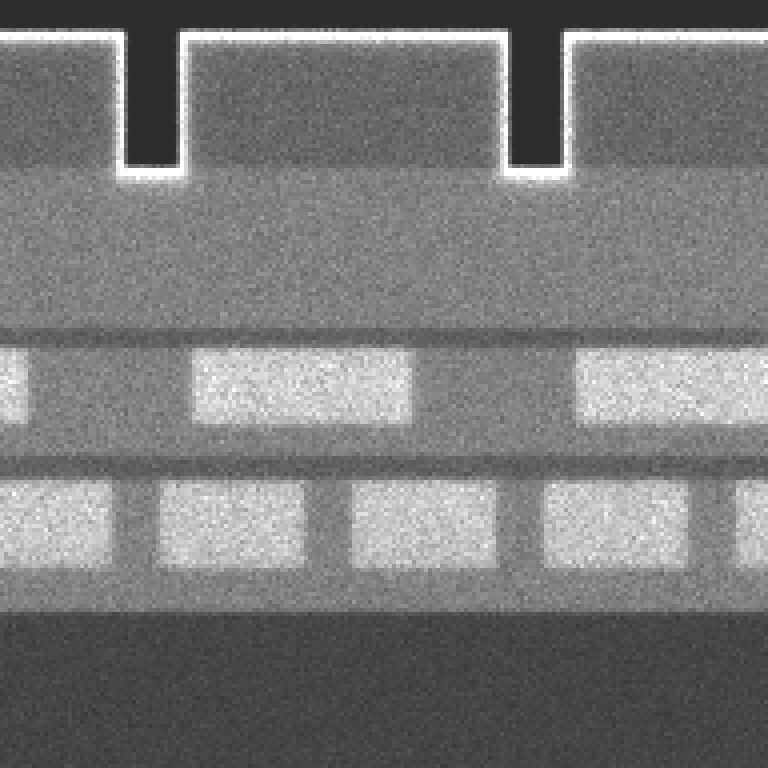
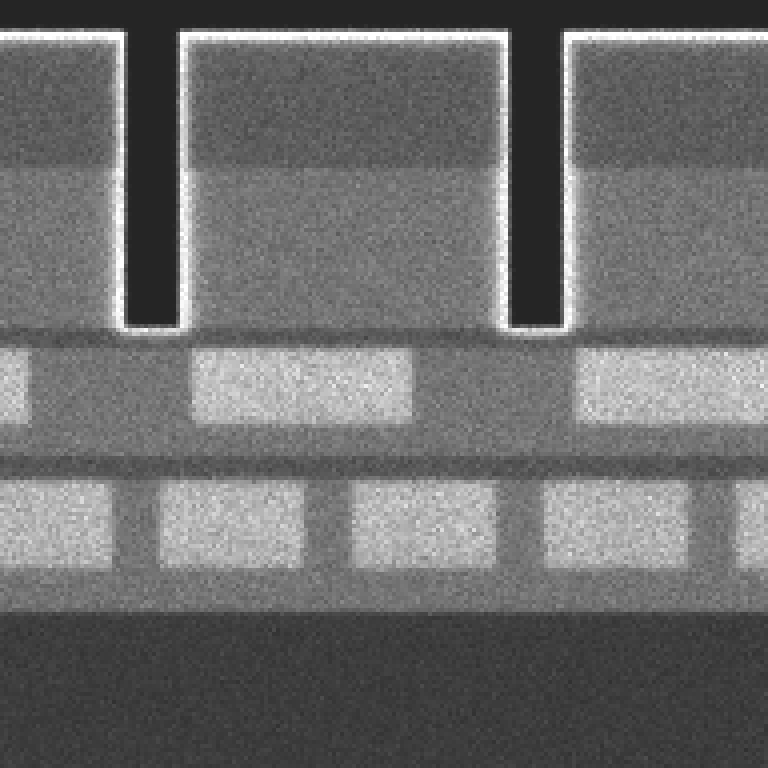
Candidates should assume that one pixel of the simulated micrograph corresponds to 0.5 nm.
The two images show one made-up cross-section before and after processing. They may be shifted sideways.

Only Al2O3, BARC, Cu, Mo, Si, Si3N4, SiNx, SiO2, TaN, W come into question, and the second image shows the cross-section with SiO2 removed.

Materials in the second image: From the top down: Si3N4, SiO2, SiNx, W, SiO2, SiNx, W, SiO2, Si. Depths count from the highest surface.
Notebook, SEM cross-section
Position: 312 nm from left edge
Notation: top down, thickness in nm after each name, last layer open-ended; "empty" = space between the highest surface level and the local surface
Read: Si3N4 68, SiO2 80, SiNx 10, W 38, SiO2 16, SiNx 12, W 44, SiO2 22, Si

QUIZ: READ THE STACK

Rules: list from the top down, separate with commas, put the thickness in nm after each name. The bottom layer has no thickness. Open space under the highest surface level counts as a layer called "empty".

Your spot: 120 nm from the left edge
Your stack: Si3N4 68, SiO2 80, SiNx 10, W 38, SiO2 16, SiNx 12, W 44, SiO2 22, Si